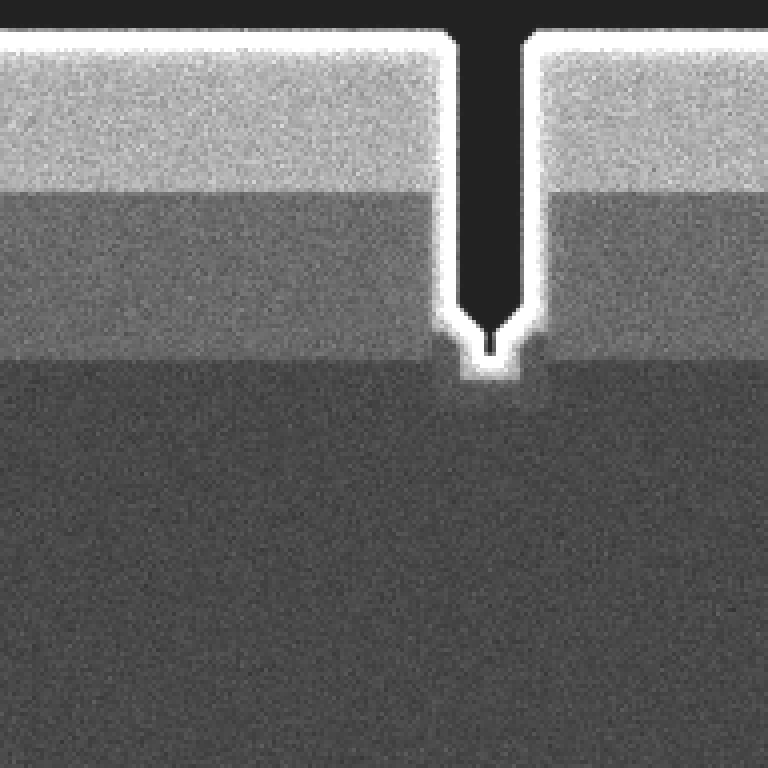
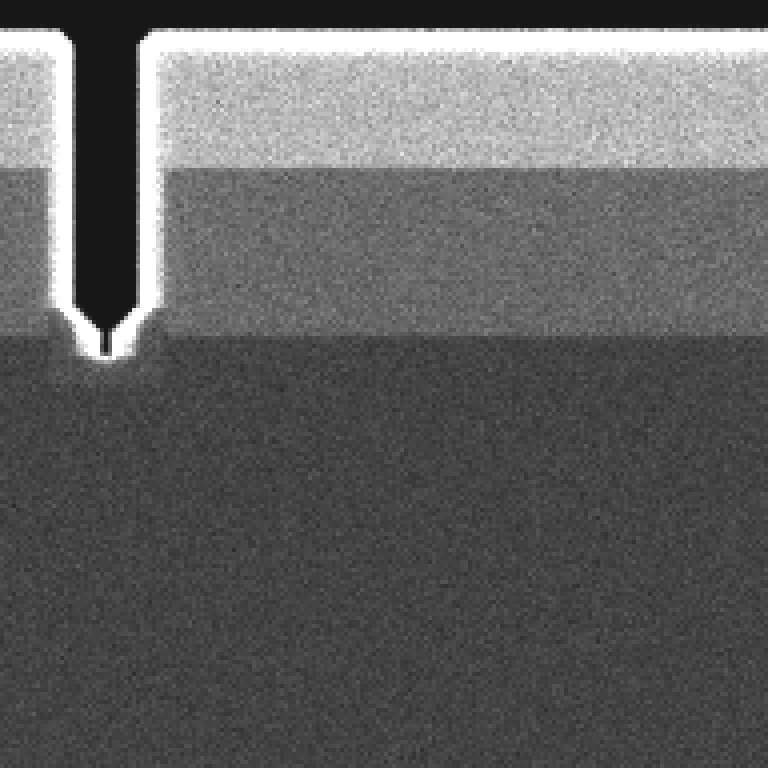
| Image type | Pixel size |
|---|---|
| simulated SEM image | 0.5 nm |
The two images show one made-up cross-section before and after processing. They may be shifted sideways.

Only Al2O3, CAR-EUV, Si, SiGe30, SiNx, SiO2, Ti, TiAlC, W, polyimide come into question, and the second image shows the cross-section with SiO2 removed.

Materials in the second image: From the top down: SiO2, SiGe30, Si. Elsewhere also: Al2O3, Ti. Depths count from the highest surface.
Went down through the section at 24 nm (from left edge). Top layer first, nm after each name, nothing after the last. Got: SiO2 138, SiGe30 38, Si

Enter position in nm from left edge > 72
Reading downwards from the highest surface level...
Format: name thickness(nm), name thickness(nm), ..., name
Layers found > empty 4, SiO2 136, SiGe30 36, Si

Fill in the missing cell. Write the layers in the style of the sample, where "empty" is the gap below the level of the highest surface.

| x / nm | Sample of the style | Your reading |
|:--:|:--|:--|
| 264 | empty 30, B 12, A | Al2O3 68, Ti 84, Si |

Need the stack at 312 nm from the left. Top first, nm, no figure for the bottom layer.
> Al2O3 68, Ti 84, Si